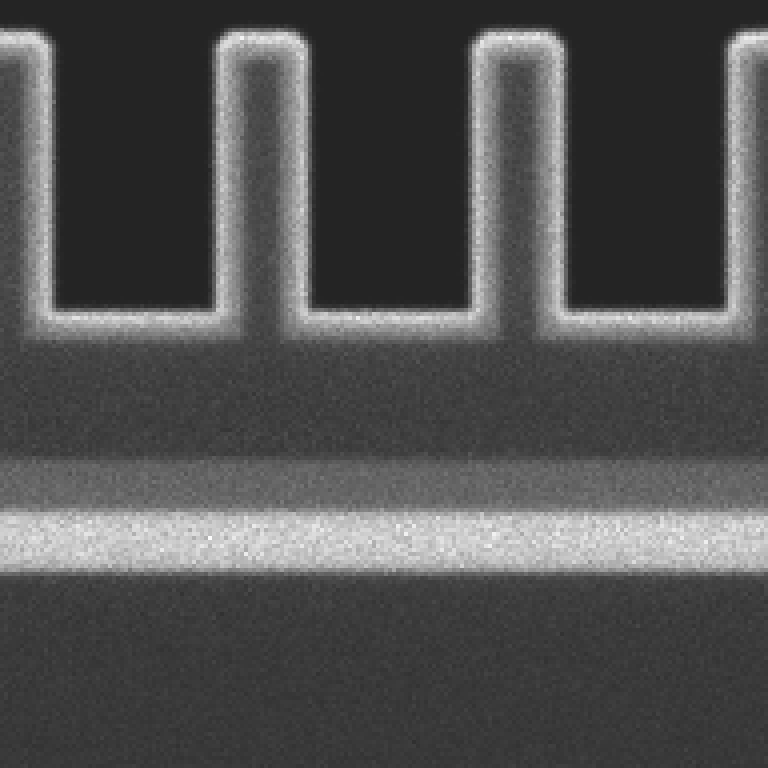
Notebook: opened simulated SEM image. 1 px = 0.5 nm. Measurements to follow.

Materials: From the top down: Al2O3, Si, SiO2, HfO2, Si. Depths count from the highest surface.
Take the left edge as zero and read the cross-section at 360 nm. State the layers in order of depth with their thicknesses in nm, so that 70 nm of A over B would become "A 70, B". empty 140, Al2O3 14, Si 60, SiO2 26, HfO2 30, Si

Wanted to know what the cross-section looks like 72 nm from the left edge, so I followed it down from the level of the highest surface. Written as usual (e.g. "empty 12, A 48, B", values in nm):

empty 140, Al2O3 14, Si 60, SiO2 26, HfO2 30, Si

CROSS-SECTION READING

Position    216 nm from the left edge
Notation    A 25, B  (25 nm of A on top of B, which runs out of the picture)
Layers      empty 140, Al2O3 14, Si 60, SiO2 26, HfO2 30, Si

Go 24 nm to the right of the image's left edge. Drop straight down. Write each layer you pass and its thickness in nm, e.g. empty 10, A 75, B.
empty 6, Al2O3 148, Si 60, SiO2 26, HfO2 30, Si